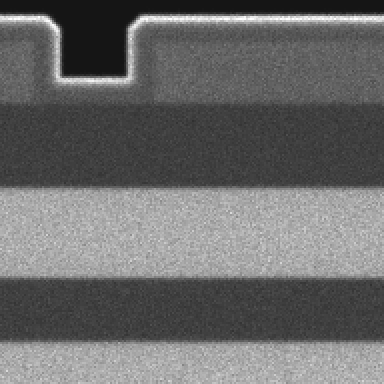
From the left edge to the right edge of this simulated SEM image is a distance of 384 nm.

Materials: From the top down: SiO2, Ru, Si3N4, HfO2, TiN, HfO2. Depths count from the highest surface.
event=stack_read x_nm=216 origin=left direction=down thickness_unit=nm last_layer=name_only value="SiO2 26, Ru 62, Si3N4 84, HfO2 90, TiN 64, HfO2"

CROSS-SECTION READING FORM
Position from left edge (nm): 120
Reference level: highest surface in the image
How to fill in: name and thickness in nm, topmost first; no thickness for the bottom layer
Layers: empty 62, SiO2 26, Si3N4 84, HfO2 90, TiN 64, HfO2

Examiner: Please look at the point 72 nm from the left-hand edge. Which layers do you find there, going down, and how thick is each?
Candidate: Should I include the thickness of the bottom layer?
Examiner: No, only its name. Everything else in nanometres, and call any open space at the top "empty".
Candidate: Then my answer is empty 62, SiO2 26, Si3N4 84, HfO2 90, TiN 64, HfO2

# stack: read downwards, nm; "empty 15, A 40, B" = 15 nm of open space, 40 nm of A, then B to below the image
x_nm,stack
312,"SiO2 26, Ru 62, Si3N4 84, HfO2 90, TiN 64, HfO2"